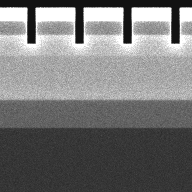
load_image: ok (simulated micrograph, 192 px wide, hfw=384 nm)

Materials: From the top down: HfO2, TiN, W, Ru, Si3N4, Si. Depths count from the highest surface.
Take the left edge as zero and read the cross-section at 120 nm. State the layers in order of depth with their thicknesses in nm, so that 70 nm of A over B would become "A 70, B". HfO2 26, TiN 28, W 42, Ru 88, Si3N4 56, Si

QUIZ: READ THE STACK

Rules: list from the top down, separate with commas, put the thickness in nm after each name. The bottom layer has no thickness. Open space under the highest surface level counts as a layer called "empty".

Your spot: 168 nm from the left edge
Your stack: HfO2 26, TiN 28, W 42, Ru 88, Si3N4 56, Si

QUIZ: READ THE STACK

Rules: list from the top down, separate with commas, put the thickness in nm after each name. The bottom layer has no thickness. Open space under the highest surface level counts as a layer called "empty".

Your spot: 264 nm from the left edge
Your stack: HfO2 26, TiN 28, W 42, Ru 88, Si3N4 56, Si